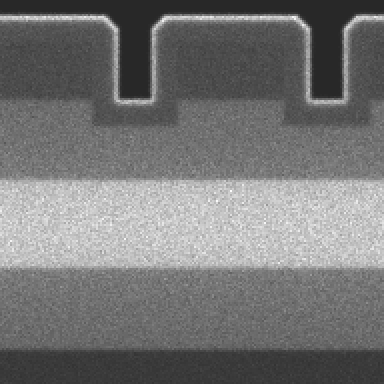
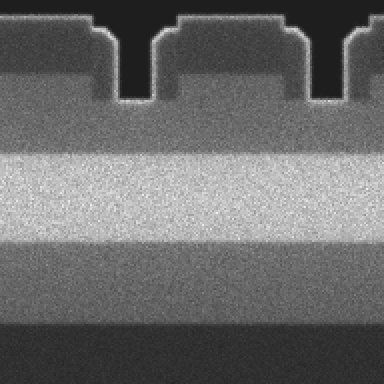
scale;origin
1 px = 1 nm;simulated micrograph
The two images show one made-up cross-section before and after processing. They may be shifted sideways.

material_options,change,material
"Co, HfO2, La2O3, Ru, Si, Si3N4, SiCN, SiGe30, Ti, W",removed,Si3N4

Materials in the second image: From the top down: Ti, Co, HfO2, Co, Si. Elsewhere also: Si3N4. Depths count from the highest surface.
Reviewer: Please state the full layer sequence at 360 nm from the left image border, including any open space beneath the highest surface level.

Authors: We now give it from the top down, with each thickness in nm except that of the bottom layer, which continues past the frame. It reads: empty 12, Si3N4 72, Co 54, HfO2 88, Co 82, Si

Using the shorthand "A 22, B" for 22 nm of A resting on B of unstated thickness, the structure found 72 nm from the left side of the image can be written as Ti 58, Co 80, HfO2 88, Co 82, Si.